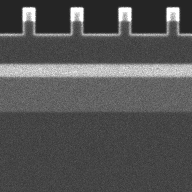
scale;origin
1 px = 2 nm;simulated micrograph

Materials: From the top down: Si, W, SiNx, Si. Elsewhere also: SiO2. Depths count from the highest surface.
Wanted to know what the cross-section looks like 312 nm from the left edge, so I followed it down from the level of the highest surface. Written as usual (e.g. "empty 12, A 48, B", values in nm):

empty 52, Si 60, W 26, SiNx 70, Si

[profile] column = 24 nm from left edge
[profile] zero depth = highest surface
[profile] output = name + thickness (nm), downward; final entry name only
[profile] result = empty 52, Si 60, W 26, SiNx 70, Si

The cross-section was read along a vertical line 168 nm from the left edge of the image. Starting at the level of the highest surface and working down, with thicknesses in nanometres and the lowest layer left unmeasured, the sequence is empty 52, Si 60, W 26, SiNx 70, Si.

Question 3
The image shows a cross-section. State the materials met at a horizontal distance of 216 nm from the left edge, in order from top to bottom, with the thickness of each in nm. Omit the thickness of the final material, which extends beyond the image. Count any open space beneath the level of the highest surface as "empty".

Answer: empty 52, Si 60, W 26, SiNx 70, Si